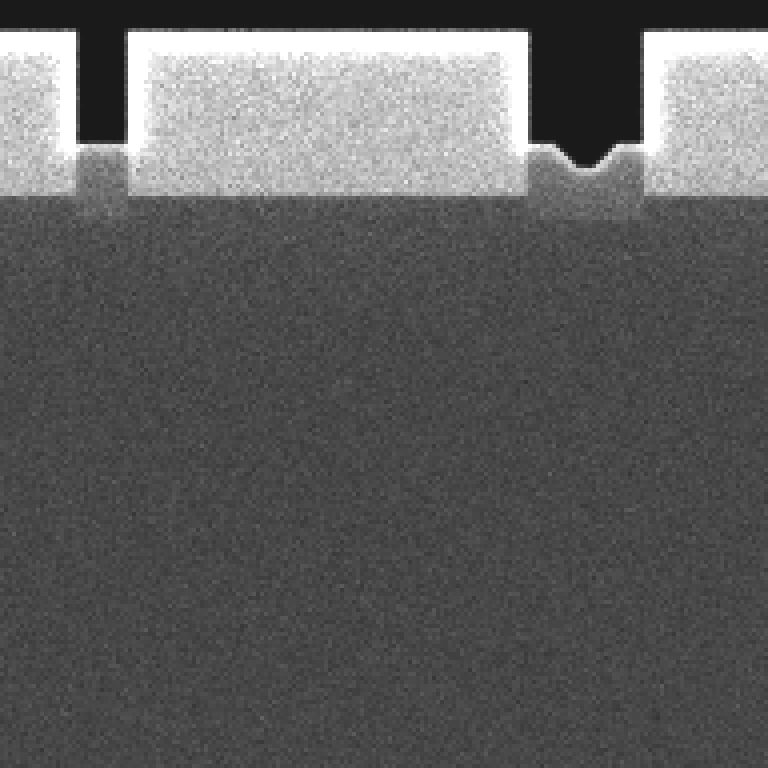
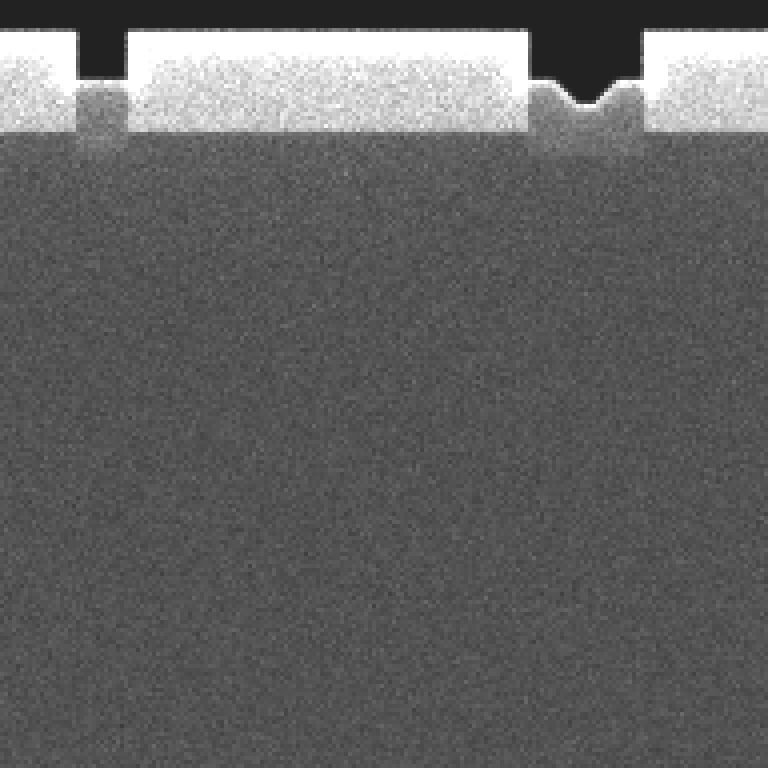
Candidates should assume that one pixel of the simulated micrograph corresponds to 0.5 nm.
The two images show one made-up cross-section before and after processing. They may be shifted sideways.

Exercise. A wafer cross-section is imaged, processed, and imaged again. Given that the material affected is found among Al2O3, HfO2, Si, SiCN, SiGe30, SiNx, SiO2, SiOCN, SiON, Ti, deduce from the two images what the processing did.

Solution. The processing removed Al2O3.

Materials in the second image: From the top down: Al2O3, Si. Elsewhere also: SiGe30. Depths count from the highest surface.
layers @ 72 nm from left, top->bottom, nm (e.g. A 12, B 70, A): Al2O3 50, Si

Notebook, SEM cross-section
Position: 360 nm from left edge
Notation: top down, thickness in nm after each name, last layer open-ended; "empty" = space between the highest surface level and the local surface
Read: Al2O3 50, Si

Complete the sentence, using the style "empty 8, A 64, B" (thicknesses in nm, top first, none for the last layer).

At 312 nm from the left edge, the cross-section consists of empty 24, SiGe30 38, Si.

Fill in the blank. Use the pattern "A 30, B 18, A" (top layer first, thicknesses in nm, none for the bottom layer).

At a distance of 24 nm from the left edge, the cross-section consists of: Al2O3 50, Si